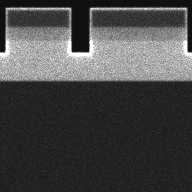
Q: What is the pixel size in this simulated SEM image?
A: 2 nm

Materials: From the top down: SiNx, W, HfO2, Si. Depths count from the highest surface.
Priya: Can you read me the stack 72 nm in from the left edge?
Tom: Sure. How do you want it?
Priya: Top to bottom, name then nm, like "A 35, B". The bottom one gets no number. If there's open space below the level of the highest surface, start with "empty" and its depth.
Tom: SiNx 38, W 28, HfO2 80, Si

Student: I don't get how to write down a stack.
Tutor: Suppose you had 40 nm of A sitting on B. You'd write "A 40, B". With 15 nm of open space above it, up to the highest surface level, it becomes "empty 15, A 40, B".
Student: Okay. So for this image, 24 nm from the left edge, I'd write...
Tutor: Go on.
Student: SiNx 38, W 28, HfO2 80, Si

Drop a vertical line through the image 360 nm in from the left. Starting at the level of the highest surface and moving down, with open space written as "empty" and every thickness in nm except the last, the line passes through SiNx 38, W 28, HfO2 80, Si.